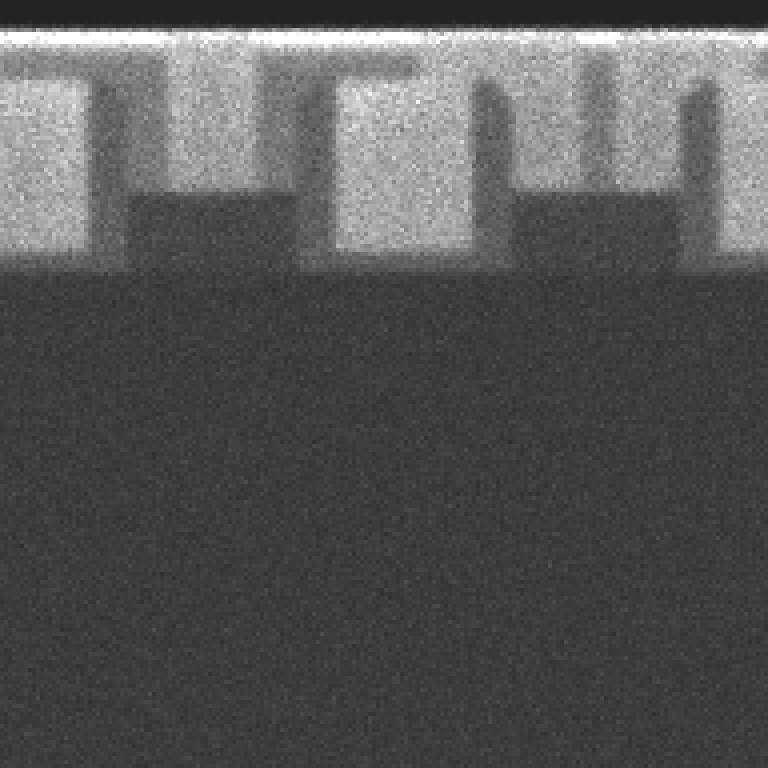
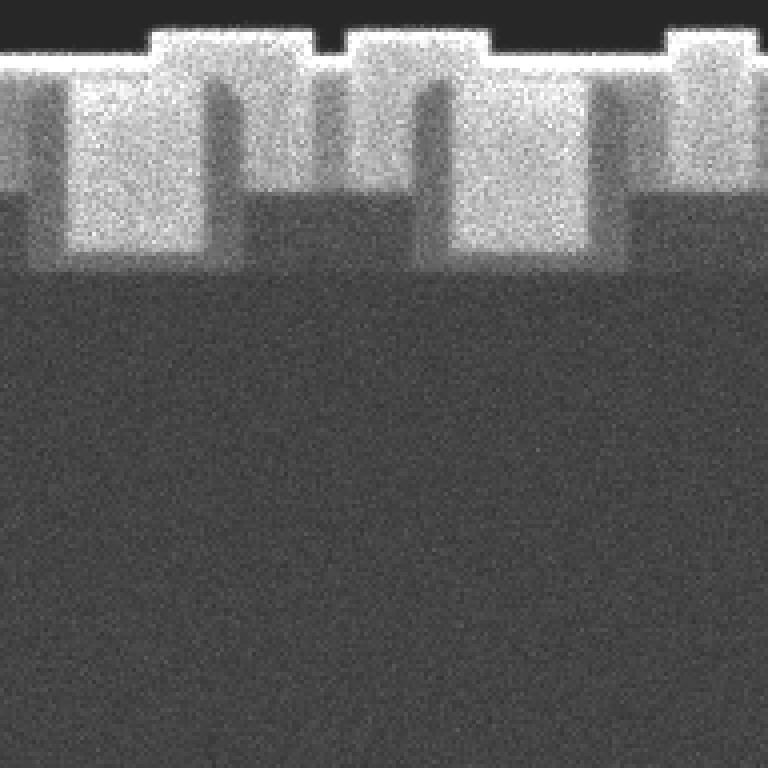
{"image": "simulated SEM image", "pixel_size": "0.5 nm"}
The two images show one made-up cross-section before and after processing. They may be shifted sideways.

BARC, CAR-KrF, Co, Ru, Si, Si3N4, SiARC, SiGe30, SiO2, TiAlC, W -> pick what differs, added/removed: SiO2 removed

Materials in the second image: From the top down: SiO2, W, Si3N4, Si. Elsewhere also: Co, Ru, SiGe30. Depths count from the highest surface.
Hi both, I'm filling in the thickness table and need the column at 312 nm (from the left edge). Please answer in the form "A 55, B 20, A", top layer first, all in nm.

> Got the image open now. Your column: empty 12, SiO2 22, Si3N4 86, Si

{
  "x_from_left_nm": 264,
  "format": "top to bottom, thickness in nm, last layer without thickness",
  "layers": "empty 12, SiO2 12, W 86, Si3N4 10, Si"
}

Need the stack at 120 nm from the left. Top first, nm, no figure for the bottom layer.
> Co 18, Ru 16, Si3N4 86, Si